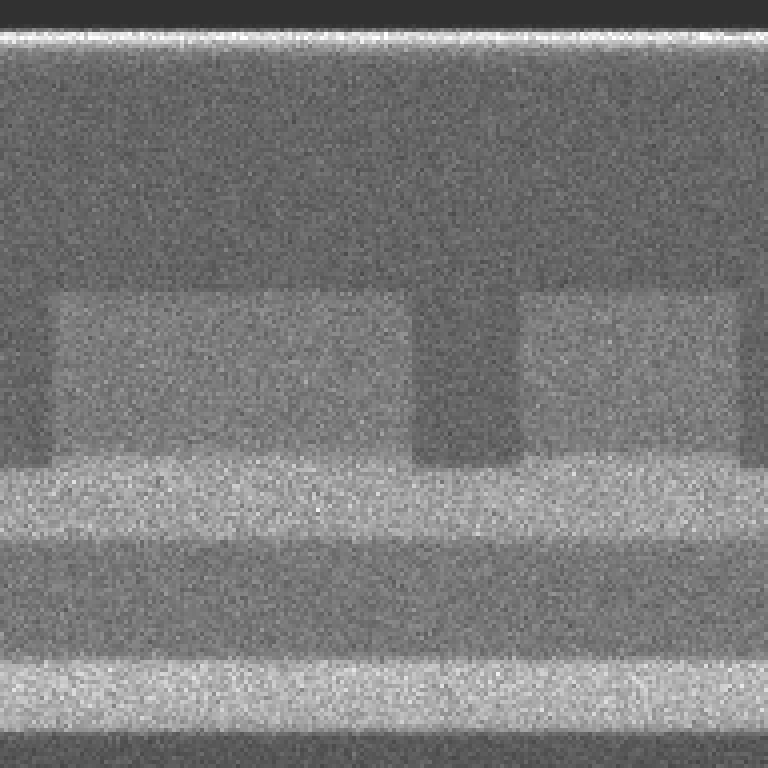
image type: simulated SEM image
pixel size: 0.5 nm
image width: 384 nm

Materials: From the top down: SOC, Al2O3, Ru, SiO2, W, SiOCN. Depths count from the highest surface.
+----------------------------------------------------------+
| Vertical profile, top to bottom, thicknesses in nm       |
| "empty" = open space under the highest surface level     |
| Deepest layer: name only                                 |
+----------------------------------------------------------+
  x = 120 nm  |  SOC 130, Al2O3 82, Ru 42, SiO2 60, W 36, SiOCN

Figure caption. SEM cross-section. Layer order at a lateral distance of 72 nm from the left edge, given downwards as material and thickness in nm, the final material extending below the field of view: SOC 130, Al2O3 82, Ru 42, SiO2 60, W 36, SiOCN